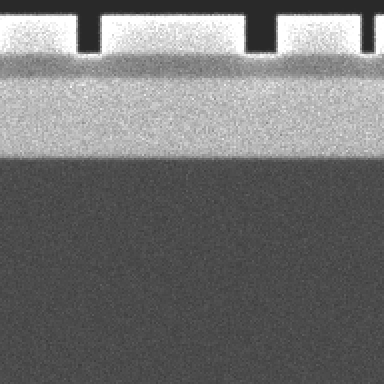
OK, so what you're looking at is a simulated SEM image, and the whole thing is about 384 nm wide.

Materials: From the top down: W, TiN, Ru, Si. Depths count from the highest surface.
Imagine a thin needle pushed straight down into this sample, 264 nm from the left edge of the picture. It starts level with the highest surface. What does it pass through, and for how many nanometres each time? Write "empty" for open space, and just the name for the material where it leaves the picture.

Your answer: empty 38, TiN 24, Ru 80, Si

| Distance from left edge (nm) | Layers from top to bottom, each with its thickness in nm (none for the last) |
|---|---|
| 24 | W 38, TiN 24, Ru 80, Si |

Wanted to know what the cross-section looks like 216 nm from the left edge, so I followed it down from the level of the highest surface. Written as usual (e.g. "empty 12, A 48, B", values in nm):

W 38, TiN 24, Ru 80, Si